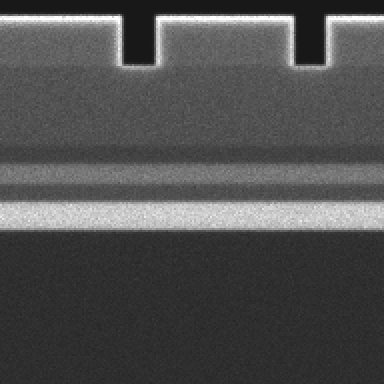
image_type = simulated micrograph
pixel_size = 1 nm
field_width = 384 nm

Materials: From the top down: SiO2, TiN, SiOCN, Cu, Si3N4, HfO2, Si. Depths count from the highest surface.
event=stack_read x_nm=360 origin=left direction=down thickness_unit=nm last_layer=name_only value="SiO2 50, TiN 80, SiOCN 18, Cu 20, Si3N4 18, HfO2 28, Si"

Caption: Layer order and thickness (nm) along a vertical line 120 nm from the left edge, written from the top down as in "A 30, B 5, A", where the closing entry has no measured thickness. SiO2 50, TiN 80, SiOCN 18, Cu 20, Si3N4 18, HfO2 28, Si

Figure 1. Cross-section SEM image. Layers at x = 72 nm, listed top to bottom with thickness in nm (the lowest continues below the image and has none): SiO2 50, TiN 80, SiOCN 18, Cu 20, Si3N4 18, HfO2 28, Si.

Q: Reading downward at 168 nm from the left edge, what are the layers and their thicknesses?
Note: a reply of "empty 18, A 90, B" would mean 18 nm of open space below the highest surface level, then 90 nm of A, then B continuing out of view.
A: SiO2 50, TiN 80, SiOCN 18, Cu 20, Si3N4 18, HfO2 28, Si